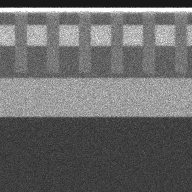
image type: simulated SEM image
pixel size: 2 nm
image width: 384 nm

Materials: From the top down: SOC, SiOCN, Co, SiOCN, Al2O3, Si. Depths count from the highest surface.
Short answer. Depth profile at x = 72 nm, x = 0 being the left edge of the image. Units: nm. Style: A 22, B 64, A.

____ SOC 6, SiOCN 28, Co 42, SiOCN 64, Al2O3 78, Si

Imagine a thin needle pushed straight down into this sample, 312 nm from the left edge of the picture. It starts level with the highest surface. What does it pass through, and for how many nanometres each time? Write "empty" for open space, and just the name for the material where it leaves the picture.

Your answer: SOC 6, SiOCN 28, Co 42, SiOCN 64, Al2O3 78, Si